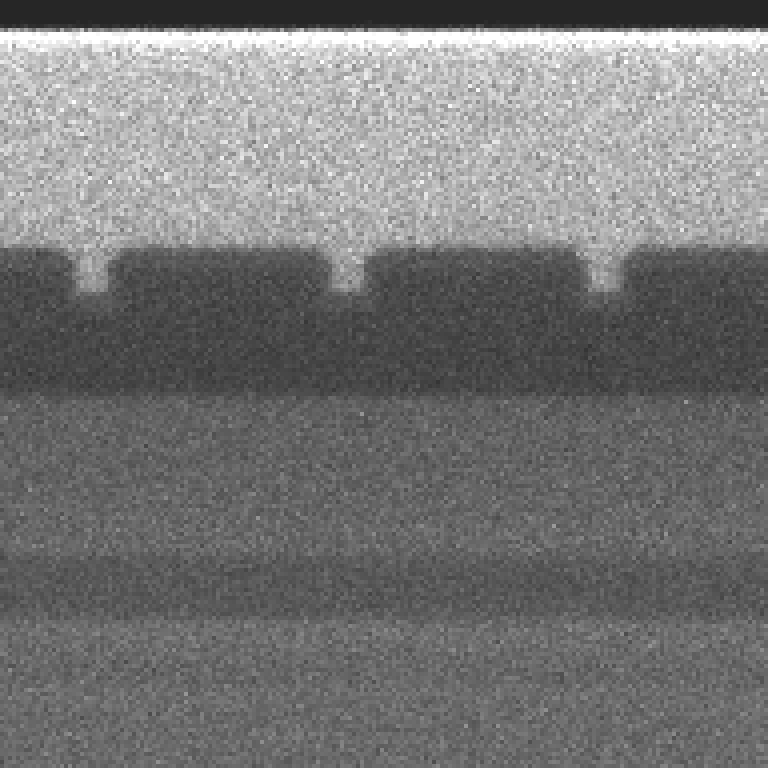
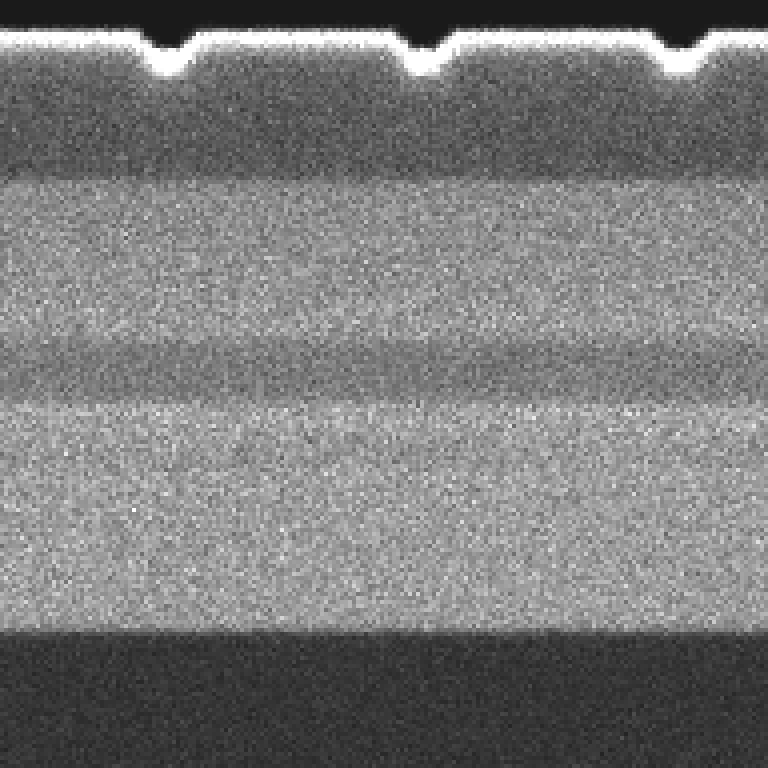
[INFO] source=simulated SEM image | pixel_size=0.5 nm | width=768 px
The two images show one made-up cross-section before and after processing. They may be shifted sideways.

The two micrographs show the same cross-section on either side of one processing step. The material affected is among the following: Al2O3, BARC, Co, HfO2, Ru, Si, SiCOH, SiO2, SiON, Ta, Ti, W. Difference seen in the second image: HfO2 removed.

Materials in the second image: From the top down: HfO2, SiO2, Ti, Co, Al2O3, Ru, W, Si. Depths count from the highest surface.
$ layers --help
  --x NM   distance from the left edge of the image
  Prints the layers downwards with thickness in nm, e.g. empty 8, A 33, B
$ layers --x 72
empty 4, SiO2 28, Ti 42, Co 80, Al2O3 32, Ru 32, W 82, Si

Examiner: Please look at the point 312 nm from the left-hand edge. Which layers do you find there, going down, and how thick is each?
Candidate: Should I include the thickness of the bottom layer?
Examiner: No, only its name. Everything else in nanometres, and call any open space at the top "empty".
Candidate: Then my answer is SiO2 10, Ti 64, Co 80, Al2O3 32, Ru 32, W 82, Si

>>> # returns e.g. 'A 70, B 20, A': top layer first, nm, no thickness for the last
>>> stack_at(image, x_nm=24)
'SiO2 10, Ti 64, Co 80, Al2O3 32, Ru 32, W 82, Si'